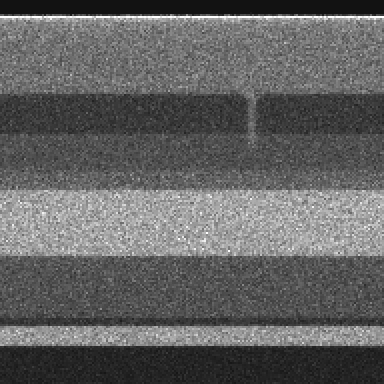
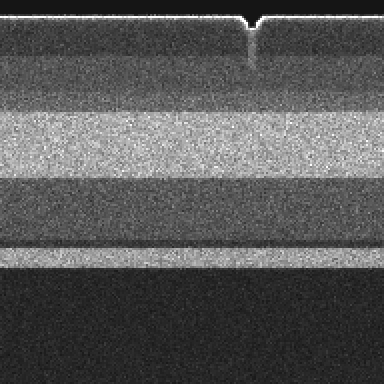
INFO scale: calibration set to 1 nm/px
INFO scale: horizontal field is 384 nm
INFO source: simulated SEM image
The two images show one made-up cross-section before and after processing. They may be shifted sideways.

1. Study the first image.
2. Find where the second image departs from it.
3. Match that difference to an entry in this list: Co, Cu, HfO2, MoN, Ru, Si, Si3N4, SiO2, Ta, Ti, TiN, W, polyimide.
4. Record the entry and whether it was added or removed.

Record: W / removed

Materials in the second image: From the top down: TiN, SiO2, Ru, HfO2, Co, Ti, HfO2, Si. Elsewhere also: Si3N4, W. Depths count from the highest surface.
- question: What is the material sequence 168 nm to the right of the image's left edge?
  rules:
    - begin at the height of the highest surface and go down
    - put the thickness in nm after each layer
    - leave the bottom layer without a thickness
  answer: TiN 40, SiO2 36, Ru 20, HfO2 66, Co 62, Ti 8, HfO2 20, Si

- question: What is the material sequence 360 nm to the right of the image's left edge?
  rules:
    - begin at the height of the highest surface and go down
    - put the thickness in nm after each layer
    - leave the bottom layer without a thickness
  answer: TiN 40, SiO2 36, Ru 20, HfO2 66, Co 62, Ti 8, HfO2 20, Si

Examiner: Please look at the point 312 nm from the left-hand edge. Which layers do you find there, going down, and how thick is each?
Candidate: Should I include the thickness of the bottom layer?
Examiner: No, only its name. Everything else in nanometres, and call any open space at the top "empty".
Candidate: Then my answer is TiN 40, SiO2 36, Ru 20, HfO2 66, Co 62, Ti 8, HfO2 20, Si